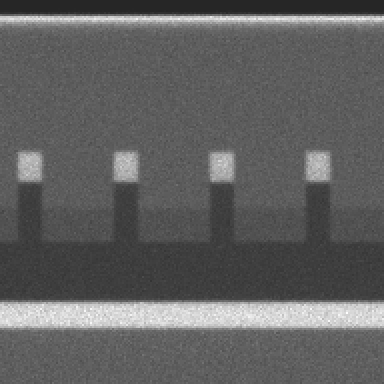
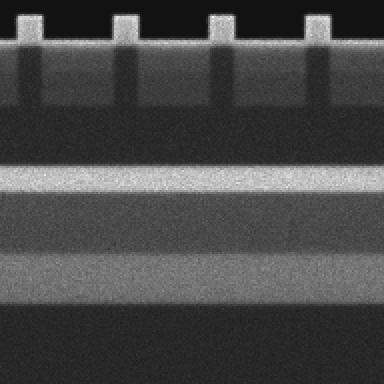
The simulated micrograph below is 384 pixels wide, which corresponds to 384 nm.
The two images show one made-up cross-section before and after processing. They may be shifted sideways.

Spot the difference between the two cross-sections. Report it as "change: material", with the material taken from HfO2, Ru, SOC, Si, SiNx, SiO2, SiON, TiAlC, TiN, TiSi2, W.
removed: SOC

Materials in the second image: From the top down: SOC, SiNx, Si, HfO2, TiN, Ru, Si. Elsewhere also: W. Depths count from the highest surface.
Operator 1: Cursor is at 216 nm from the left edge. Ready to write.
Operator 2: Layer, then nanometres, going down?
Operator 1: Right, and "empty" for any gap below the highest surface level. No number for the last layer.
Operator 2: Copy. W 30, Si 120, HfO2 26, TiN 62, Ru 50, Si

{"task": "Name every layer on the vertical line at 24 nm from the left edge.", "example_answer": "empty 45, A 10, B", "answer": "W 30, Si 120, HfO2 26, TiN 62, Ru 50, Si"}